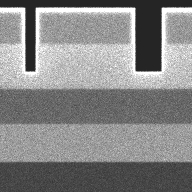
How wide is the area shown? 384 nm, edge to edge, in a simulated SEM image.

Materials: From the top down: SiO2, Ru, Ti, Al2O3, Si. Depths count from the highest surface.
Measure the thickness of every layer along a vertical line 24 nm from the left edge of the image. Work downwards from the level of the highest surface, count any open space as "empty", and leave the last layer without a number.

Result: SiO2 72, Ru 90, Ti 70, Al2O3 76, Si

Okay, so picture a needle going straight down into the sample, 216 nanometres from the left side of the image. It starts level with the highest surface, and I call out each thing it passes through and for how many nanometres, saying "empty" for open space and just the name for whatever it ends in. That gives SiO2 72, Ru 90, Ti 70, Al2O3 76, Si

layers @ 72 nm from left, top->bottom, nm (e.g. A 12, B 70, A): SiO2 72, Ru 90, Ti 70, Al2O3 76, Si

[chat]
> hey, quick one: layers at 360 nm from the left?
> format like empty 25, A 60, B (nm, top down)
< SiO2 72, Ru 90, Ti 70, Al2O3 76, Si